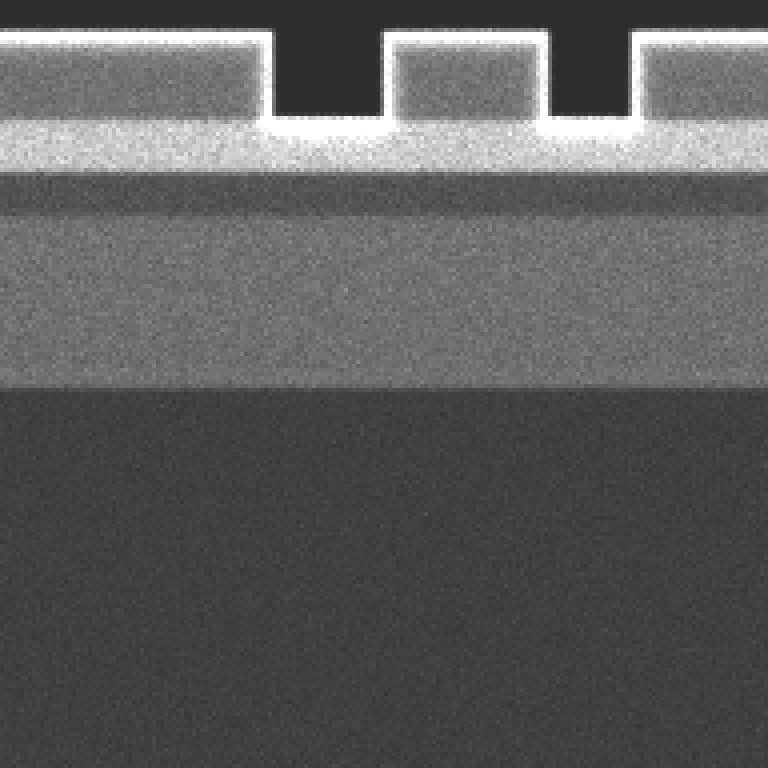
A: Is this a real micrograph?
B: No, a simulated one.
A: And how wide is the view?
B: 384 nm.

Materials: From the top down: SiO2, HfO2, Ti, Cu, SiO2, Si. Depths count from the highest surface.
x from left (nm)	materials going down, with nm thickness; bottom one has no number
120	SiO2 44, HfO2 26, Ti 22, Cu 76, SiO2 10, Si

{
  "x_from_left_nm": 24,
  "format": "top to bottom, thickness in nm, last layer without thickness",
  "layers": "SiO2 44, HfO2 26, Ti 22, Cu 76, SiO2 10, Si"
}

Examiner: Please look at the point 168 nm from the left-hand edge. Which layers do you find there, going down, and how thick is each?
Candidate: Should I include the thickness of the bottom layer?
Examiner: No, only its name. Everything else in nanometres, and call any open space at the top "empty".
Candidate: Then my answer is empty 44, HfO2 26, Ti 22, Cu 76, SiO2 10, Si